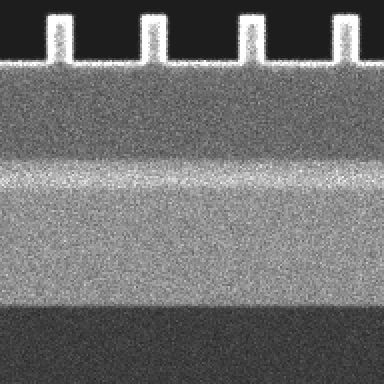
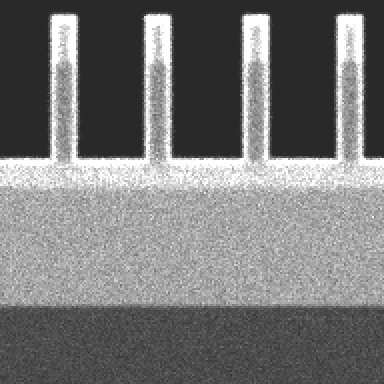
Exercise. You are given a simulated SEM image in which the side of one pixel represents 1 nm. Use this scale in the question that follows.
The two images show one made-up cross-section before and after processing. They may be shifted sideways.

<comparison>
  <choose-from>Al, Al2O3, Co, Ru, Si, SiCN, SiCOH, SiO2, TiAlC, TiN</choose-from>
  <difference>TiN removed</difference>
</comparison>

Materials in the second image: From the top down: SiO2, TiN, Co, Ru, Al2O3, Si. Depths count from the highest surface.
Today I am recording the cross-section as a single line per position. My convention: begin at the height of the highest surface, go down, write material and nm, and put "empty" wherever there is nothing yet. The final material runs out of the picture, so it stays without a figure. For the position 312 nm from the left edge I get empty 144, Co 12, Ru 16, Al2O3 118, Si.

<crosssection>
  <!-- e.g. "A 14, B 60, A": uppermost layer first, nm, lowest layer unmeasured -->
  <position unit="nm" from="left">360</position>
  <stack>SiO2 46, TiN 98, Co 12, Ru 16, Al2O3 118, Si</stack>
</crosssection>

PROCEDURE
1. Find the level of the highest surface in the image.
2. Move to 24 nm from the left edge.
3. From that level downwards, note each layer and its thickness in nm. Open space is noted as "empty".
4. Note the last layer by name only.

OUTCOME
empty 144, Co 12, Ru 16, Al2O3 118, Si